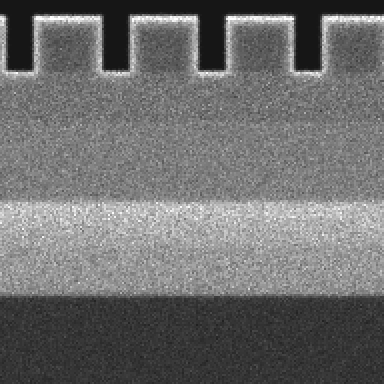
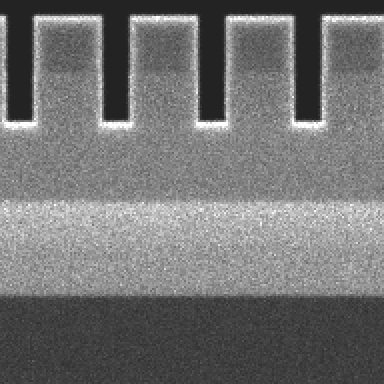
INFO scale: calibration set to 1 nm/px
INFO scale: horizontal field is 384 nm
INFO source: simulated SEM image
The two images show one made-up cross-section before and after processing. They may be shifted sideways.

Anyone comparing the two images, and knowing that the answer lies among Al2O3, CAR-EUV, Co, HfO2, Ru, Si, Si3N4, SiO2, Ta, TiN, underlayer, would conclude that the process removed TiN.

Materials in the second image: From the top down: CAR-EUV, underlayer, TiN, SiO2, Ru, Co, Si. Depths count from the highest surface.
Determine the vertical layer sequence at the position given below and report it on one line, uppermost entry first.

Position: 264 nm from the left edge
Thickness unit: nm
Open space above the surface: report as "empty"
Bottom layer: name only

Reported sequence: CAR-EUV 34, underlayer 22, TiN 50, SiO2 80, Ru 44, Co 50, Si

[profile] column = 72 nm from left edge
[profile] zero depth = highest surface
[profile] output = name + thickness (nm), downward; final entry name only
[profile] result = CAR-EUV 34, underlayer 22, TiN 50, SiO2 80, Ru 44, Co 50, Si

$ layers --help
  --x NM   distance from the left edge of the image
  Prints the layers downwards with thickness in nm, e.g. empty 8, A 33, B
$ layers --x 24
empty 106, SiO2 80, Ru 44, Co 50, Si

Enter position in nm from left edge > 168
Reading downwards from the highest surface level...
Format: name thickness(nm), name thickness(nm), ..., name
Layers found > CAR-EUV 34, underlayer 22, TiN 50, SiO2 80, Ru 44, Co 50, Si